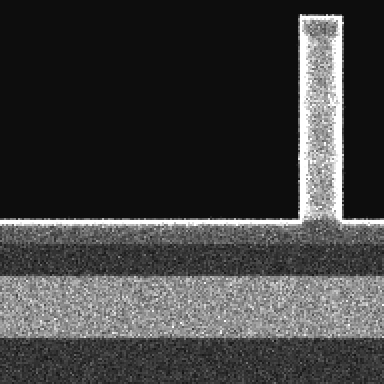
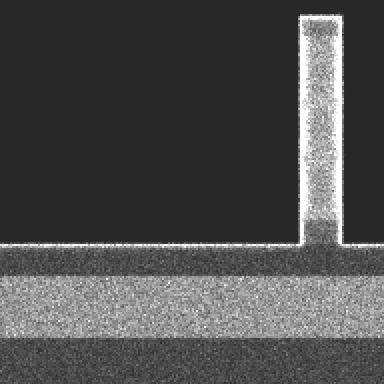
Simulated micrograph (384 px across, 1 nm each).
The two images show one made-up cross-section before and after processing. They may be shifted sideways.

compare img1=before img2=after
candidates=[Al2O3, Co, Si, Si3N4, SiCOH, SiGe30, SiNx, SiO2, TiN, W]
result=removed:SiNx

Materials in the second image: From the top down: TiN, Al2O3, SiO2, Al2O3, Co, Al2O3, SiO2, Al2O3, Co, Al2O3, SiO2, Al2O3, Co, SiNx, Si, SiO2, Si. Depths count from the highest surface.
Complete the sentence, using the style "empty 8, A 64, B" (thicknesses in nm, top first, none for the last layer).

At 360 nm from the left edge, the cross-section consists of empty 228, Si 32, SiO2 62, Si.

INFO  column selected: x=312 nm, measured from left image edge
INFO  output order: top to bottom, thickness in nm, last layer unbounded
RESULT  TiN 20, Al2O3 30, SiO2 16, Al2O3 14, Co 12, Al2O3 14, SiO2 16, Al2O3 14, Co 12, Al2O3 14, SiO2 16, Al2O3 14, Co 12, SiNx 24, Si 32, SiO2 62, Si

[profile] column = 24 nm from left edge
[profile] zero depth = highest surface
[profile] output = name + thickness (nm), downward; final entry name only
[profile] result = empty 228, Si 32, SiO2 62, Si